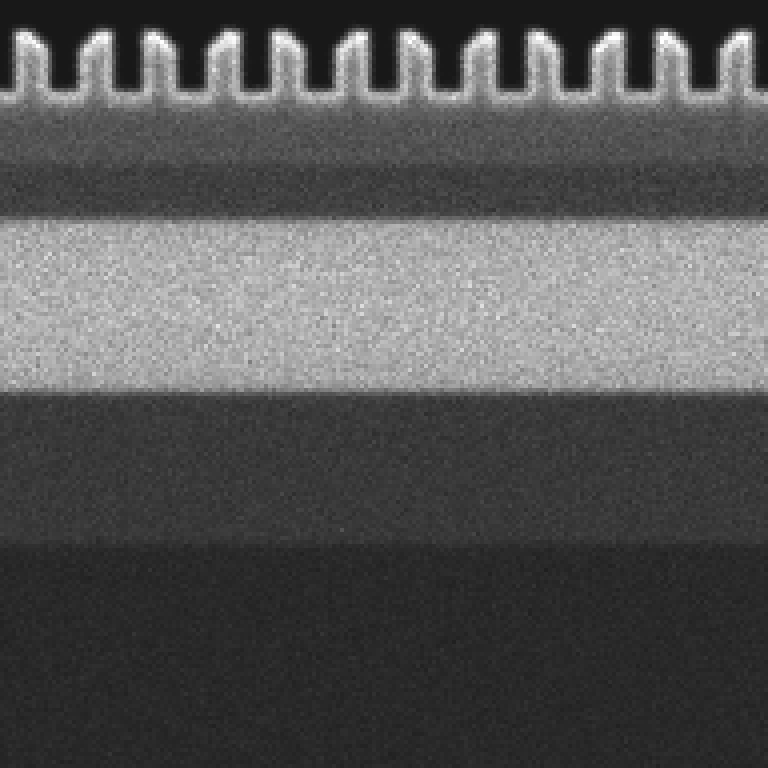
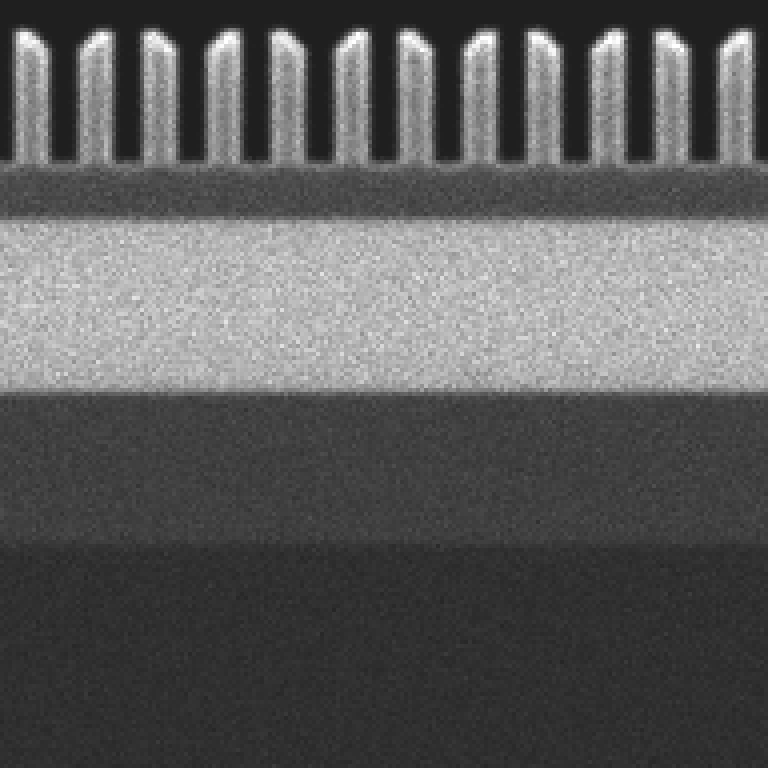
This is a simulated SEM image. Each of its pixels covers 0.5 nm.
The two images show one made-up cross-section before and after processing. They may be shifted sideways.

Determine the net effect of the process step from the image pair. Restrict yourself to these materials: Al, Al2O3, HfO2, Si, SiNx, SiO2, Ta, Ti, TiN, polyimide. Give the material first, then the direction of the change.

SiO2: removed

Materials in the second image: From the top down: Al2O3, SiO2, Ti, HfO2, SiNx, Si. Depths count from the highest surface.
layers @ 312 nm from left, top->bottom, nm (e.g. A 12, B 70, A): empty 66, Ti 28, HfO2 86, SiNx 76, Si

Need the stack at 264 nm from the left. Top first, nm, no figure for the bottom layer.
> Al2O3 30, SiO2 36, Ti 28, HfO2 86, SiNx 76, Si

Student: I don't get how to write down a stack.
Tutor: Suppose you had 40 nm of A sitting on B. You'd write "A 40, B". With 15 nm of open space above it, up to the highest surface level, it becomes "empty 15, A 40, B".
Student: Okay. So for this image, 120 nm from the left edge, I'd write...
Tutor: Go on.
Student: empty 66, Ti 28, HfO2 86, SiNx 76, Si